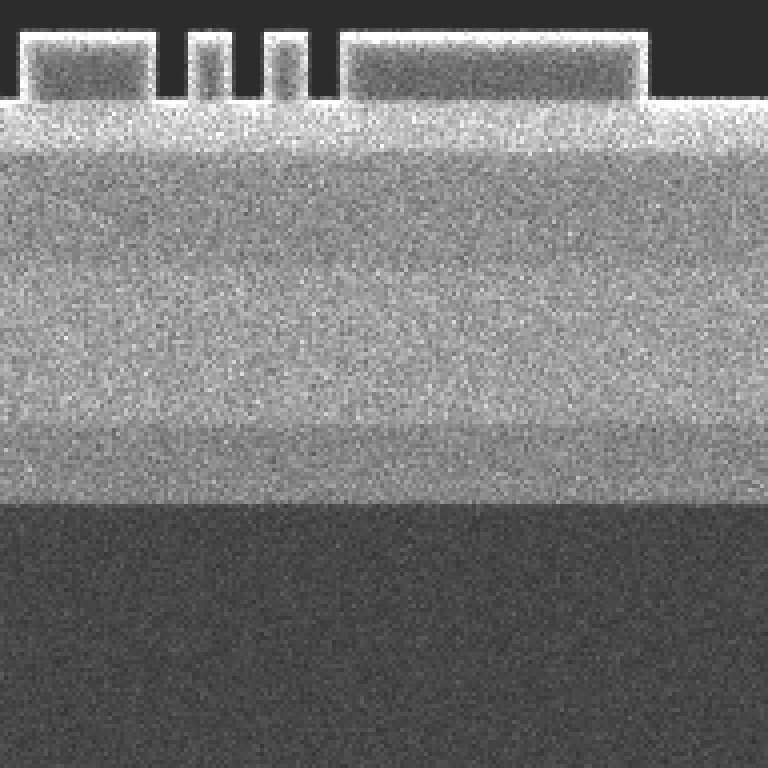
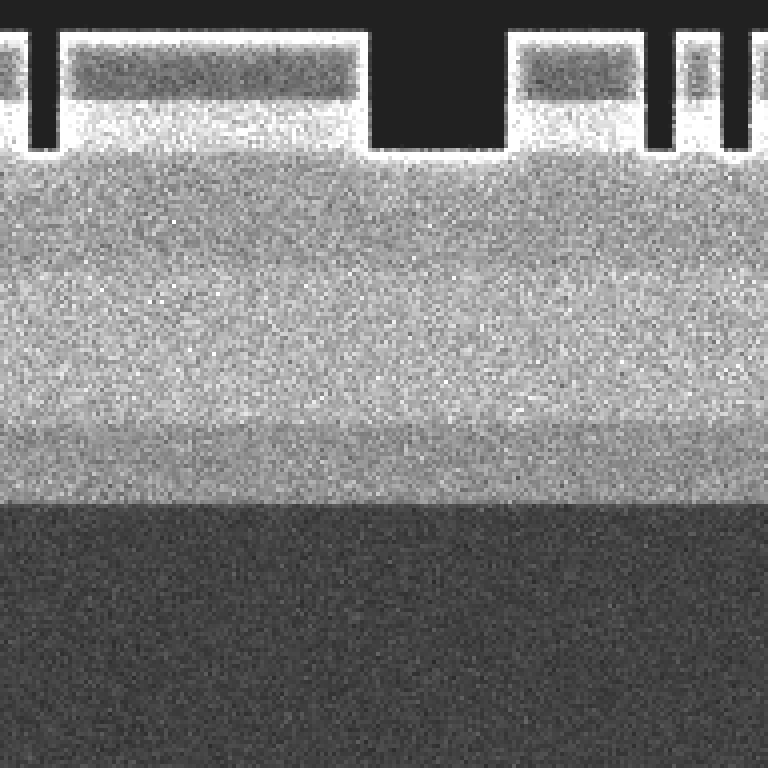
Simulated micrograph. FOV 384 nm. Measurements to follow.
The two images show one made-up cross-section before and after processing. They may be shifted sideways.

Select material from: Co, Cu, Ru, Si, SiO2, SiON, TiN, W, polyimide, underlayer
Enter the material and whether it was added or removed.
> W / removed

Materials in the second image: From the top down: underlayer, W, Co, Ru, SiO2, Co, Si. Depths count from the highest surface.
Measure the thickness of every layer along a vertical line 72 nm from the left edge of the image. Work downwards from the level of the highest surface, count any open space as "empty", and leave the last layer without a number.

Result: underlayer 34, W 26, Co 58, Ru 78, SiO2 28, Co 12, Si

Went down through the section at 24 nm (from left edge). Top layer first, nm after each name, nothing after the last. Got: empty 60, Co 58, Ru 78, SiO2 28, Co 12, Si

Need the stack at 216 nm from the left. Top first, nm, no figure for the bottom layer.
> empty 60, Co 58, Ru 78, SiO2 28, Co 12, Si